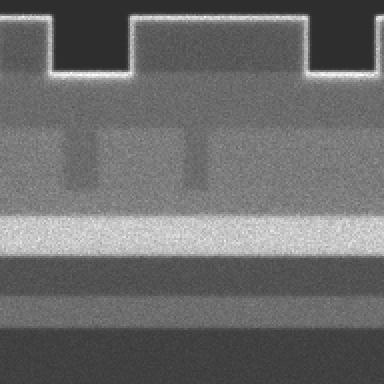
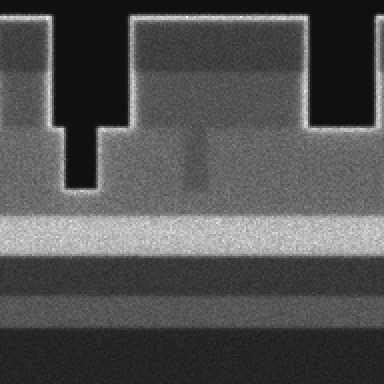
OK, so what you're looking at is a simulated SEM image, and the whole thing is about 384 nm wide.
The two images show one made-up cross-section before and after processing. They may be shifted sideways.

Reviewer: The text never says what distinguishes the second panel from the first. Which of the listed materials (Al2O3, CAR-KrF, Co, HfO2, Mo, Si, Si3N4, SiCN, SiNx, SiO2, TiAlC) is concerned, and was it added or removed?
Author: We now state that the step removed SiO2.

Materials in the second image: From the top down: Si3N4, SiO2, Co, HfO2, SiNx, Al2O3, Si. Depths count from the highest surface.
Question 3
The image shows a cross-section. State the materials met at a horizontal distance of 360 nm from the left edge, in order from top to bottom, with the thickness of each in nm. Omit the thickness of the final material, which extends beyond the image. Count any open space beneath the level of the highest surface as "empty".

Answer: empty 112, Co 88, HfO2 40, SiNx 40, Al2O3 32, Si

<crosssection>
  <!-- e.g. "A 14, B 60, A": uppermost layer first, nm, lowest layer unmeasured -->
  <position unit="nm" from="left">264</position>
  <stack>Si3N4 56, SiO2 56, Co 88, HfO2 40, SiNx 40, Al2O3 32, Si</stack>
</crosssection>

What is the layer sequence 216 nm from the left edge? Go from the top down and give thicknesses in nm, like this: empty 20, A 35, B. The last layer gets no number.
Si3N4 56, SiO2 56, Co 88, HfO2 40, SiNx 40, Al2O3 32, Si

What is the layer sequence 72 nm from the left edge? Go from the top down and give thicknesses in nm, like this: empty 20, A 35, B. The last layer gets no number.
empty 174, Co 26, HfO2 40, SiNx 40, Al2O3 32, Si